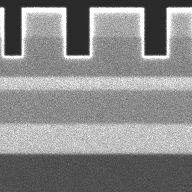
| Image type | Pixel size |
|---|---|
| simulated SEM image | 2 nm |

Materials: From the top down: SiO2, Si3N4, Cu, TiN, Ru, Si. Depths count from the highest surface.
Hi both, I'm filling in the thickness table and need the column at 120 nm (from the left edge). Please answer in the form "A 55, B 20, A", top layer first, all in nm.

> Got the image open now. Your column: SiO2 58, Si3N4 80, Cu 26, TiN 68, Ru 60, Si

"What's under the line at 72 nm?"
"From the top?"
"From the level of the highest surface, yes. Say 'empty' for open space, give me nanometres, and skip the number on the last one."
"SiO2 58, Si3N4 80, Cu 26, TiN 68, Ru 60, Si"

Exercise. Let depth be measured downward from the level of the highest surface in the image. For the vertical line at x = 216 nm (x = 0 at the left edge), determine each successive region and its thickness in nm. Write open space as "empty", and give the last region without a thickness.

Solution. SiO2 58, Si3N4 80, Cu 26, TiN 68, Ru 60, Si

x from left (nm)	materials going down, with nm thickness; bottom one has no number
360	SiO2 58, Si3N4 80, Cu 26, TiN 68, Ru 60, Si